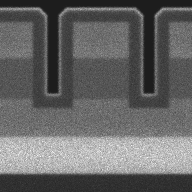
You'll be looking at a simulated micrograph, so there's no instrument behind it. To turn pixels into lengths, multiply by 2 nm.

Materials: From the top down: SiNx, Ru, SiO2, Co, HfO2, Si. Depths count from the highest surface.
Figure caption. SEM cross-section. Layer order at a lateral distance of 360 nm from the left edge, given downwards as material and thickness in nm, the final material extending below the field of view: SiNx 28, Ru 72, SiO2 82, Co 76, HfO2 74, Si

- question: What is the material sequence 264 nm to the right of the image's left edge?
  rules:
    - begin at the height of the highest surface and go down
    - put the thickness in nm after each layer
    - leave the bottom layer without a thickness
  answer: SiNx 200, Co 58, HfO2 74, Si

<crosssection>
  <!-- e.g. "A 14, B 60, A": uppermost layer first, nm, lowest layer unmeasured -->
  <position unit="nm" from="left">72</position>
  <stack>SiNx 200, Co 58, HfO2 74, Si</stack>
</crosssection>